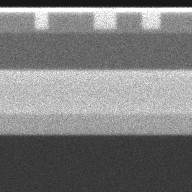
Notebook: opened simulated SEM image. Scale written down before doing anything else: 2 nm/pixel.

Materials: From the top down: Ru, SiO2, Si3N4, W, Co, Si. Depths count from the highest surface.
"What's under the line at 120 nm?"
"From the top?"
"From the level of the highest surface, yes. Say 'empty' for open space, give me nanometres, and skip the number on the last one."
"SiO2 50, Si3N4 74, W 88, Co 42, Si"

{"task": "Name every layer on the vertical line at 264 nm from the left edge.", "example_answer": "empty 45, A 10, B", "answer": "SiO2 50, Si3N4 74, W 88, Co 42, Si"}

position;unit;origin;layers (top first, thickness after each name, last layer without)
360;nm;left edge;SiO2 50, Si3N4 74, W 88, Co 42, Si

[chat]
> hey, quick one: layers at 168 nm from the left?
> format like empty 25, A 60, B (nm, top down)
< SiO2 50, Si3N4 74, W 88, Co 42, Si